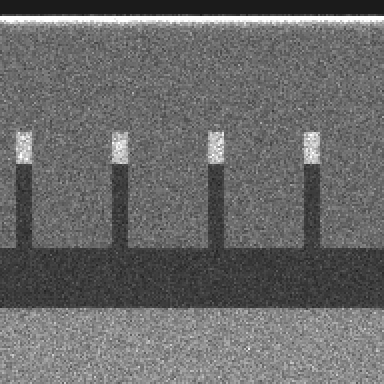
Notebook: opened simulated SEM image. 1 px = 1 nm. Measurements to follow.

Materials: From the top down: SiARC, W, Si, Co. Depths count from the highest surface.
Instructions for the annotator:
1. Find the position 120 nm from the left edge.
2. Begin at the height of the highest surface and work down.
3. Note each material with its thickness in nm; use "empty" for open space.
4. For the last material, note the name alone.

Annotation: SiARC 116, W 32, Si 144, Co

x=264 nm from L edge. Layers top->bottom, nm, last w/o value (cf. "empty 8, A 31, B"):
SiARC 232, Si 60, Co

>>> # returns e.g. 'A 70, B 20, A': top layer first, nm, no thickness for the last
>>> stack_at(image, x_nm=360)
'SiARC 232, Si 60, Co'